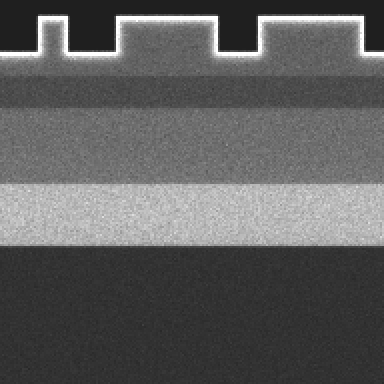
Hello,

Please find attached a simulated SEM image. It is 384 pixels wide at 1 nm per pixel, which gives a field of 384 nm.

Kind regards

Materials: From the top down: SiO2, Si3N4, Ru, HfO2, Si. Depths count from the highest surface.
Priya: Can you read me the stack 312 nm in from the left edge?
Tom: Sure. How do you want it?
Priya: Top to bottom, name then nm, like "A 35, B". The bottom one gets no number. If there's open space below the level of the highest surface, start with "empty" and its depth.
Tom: SiO2 60, Si3N4 32, Ru 76, HfO2 62, Si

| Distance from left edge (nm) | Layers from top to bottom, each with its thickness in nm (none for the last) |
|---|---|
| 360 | SiO2 60, Si3N4 32, Ru 76, HfO2 62, Si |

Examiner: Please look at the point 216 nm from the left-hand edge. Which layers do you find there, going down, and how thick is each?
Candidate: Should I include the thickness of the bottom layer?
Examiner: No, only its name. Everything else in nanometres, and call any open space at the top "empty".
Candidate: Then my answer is SiO2 60, Si3N4 32, Ru 76, HfO2 62, Si